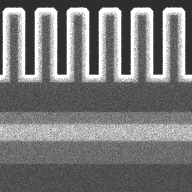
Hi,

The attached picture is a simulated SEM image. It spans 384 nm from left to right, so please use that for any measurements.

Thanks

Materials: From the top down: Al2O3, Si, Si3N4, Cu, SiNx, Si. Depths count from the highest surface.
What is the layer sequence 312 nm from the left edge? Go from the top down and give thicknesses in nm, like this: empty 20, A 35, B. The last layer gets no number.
empty 134, Al2O3 14, Si 60, Si3N4 24, Cu 34, SiNx 46, Si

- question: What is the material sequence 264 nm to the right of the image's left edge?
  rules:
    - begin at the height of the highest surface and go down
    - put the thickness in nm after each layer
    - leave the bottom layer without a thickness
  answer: empty 4, Al2O3 144, Si 60, Si3N4 24, Cu 34, SiNx 46, Si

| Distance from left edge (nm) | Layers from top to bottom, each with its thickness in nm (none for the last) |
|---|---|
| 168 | Al2O3 148, Si 60, Si3N4 24, Cu 34, SiNx 46, Si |